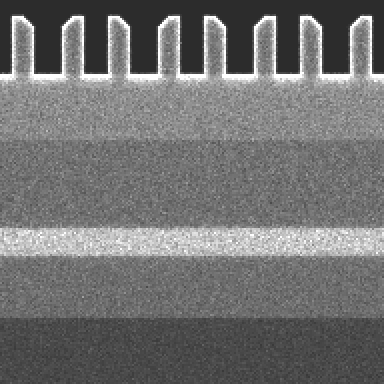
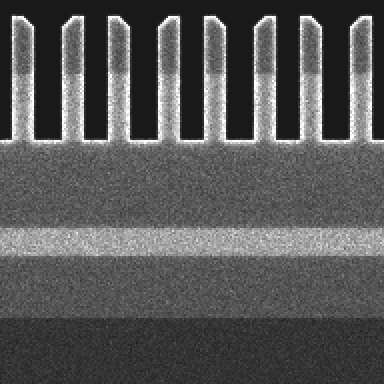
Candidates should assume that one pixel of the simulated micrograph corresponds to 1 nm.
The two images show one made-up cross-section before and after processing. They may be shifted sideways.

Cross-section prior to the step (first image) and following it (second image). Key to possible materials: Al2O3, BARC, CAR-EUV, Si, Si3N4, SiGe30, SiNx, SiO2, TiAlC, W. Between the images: SiO2 was removed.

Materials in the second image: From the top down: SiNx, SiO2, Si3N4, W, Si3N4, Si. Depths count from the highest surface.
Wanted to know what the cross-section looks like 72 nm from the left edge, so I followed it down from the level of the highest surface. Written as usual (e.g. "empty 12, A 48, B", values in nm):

SiNx 58, SiO2 66, Si3N4 88, W 28, Si3N4 62, Si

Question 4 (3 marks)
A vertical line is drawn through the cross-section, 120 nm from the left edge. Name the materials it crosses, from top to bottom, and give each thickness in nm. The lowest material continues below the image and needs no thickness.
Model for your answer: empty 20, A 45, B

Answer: empty 2, SiNx 56, SiO2 66, Si3N4 88, W 28, Si3N4 62, Si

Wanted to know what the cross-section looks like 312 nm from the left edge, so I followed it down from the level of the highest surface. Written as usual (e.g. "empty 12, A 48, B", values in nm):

empty 2, SiNx 56, SiO2 66, Si3N4 88, W 28, Si3N4 62, Si